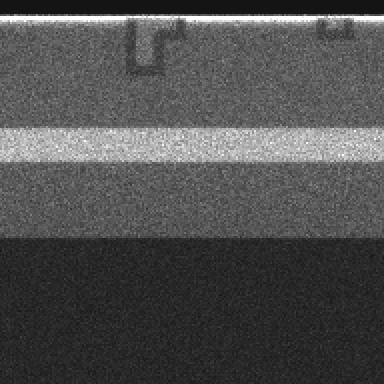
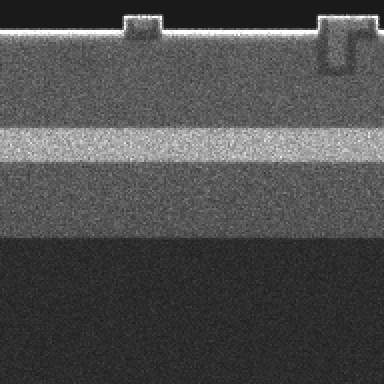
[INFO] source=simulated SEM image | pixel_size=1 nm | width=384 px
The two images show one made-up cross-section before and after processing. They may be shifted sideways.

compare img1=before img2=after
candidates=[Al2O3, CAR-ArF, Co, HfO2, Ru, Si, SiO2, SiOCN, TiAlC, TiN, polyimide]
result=removed:SiO2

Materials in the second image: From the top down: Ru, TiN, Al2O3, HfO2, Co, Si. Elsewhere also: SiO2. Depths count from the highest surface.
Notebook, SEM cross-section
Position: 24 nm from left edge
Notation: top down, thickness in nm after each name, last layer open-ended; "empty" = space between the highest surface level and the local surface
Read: empty 14, SiO2 10, Al2O3 88, HfO2 34, Co 76, Si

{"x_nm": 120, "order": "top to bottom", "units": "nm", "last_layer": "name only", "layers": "empty 14, SiO2 10, Al2O3 88, HfO2 34, Co 76, Si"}